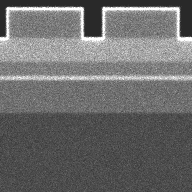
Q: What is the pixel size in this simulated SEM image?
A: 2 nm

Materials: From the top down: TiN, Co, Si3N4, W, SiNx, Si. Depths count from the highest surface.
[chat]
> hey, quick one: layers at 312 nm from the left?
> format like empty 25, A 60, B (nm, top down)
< TiN 60, Co 48, Si3N4 28, W 8, SiNx 66, Si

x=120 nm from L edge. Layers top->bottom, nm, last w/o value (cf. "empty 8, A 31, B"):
TiN 60, Co 48, Si3N4 28, W 8, SiNx 66, Si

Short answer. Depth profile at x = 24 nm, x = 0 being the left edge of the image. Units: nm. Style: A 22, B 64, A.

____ TiN 60, Co 48, Si3N4 28, W 8, SiNx 66, Si